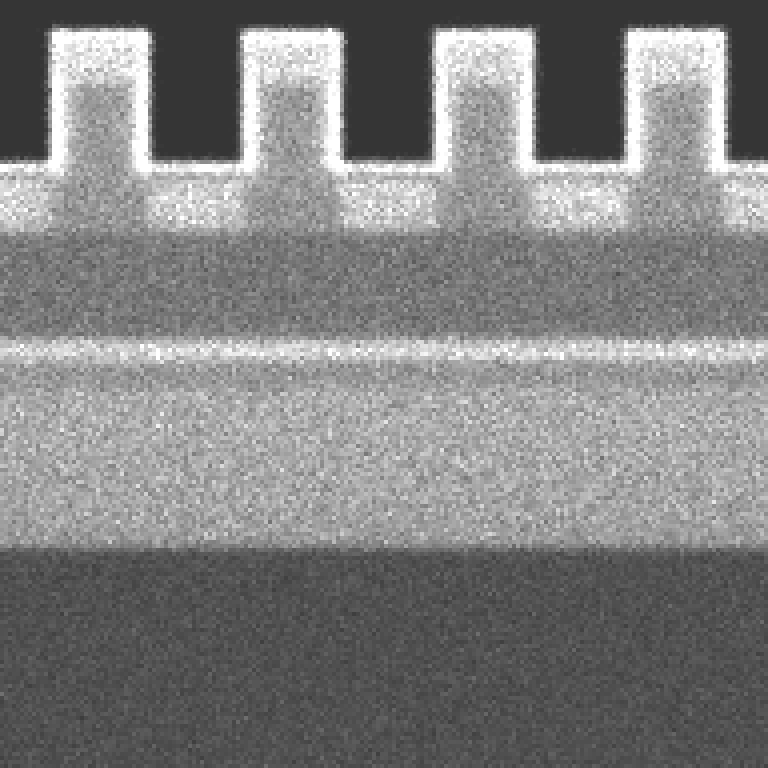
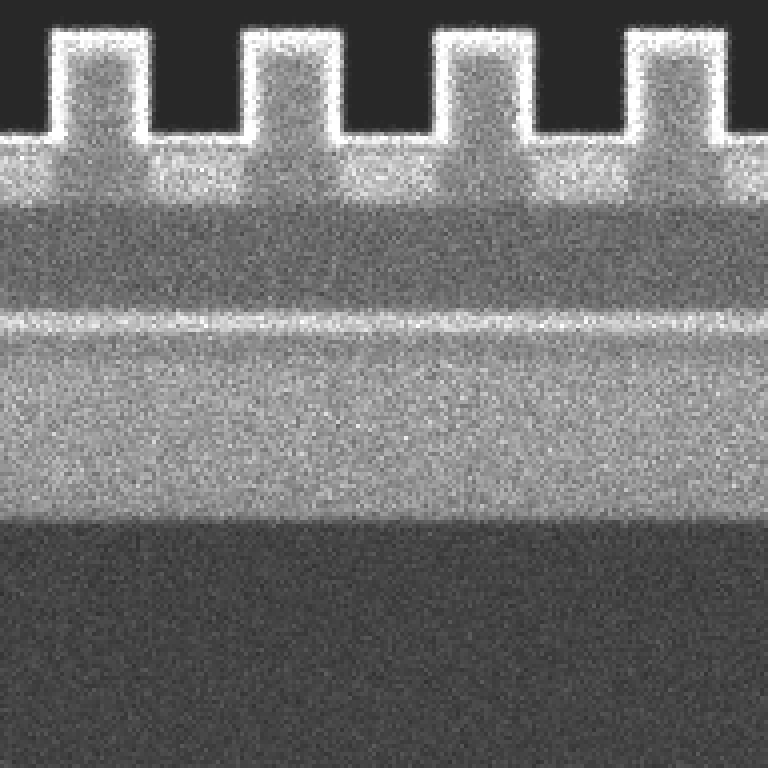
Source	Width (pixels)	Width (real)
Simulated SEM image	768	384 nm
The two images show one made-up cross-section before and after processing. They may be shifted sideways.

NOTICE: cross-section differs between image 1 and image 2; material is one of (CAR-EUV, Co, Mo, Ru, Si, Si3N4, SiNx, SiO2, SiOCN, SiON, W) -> removed: Ru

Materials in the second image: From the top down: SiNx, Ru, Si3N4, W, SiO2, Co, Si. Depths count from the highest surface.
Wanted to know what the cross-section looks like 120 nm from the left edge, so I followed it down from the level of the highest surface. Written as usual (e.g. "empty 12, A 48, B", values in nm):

empty 52, SiNx 8, Ru 26, Si3N4 54, W 10, SiO2 14, Co 80, Si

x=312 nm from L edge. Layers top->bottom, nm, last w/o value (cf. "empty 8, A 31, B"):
empty 52, SiNx 8, Ru 26, Si3N4 54, W 10, SiO2 14, Co 80, Si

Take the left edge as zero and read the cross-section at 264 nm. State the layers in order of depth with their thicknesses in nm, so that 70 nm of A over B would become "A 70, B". Ru 12, SiO2 74, Si3N4 54, W 10, SiO2 14, Co 80, Si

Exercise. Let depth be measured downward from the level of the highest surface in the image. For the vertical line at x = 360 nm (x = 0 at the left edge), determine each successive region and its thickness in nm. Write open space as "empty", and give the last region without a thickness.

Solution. Ru 12, SiO2 74, Si3N4 54, W 10, SiO2 14, Co 80, Si